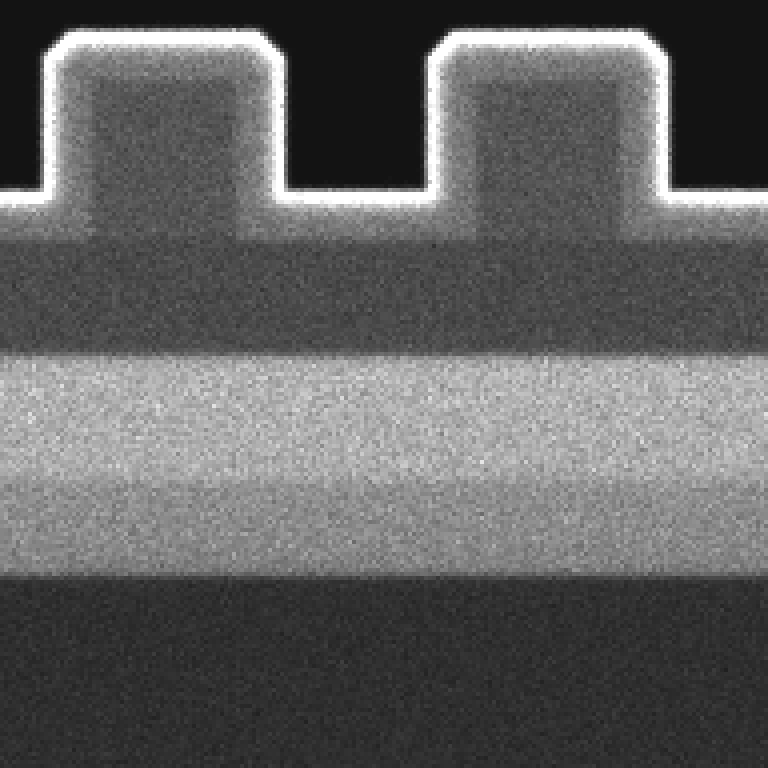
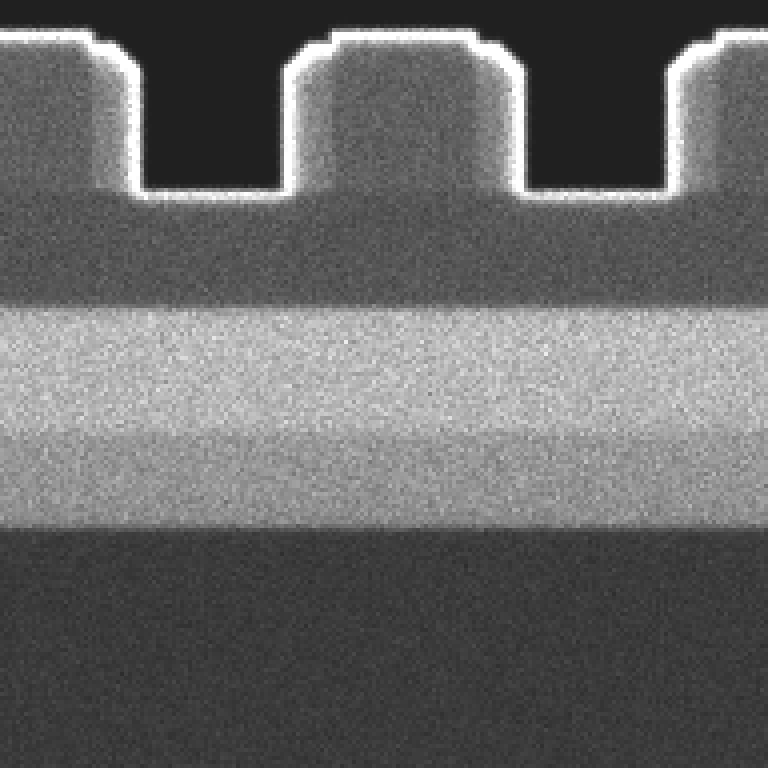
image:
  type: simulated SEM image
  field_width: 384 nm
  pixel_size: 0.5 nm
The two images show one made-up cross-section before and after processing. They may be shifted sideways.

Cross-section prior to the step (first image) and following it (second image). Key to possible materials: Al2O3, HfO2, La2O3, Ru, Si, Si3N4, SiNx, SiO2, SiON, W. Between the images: SiO2 was removed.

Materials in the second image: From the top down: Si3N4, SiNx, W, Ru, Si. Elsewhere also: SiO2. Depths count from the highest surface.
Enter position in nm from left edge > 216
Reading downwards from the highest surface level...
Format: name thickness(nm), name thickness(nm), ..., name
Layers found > Si3N4 80, SiNx 58, W 62, Ru 48, Si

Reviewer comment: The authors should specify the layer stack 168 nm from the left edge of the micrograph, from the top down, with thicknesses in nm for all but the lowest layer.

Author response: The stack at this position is Si3N4 80, SiNx 58, W 62, Ru 48, Si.